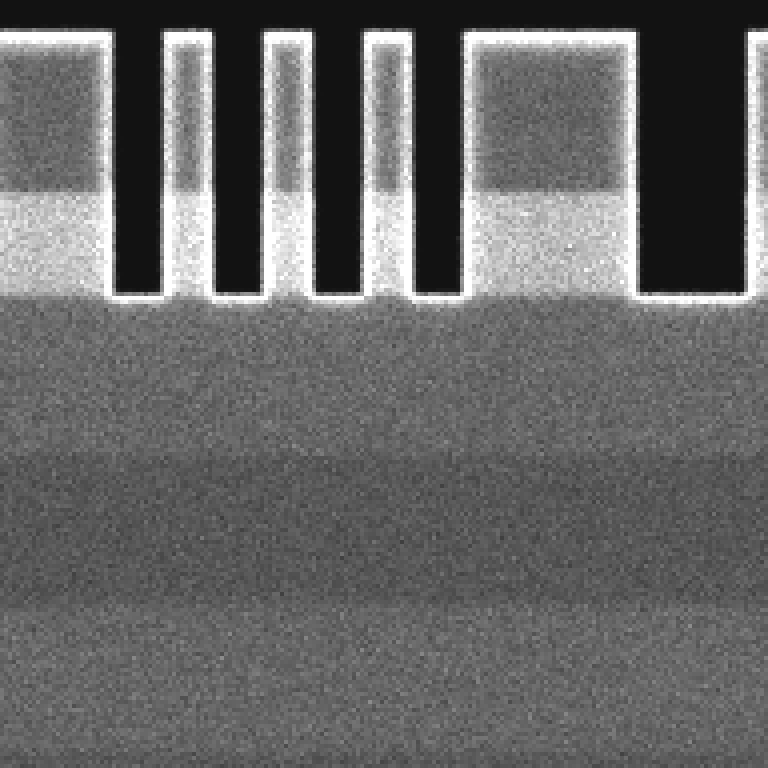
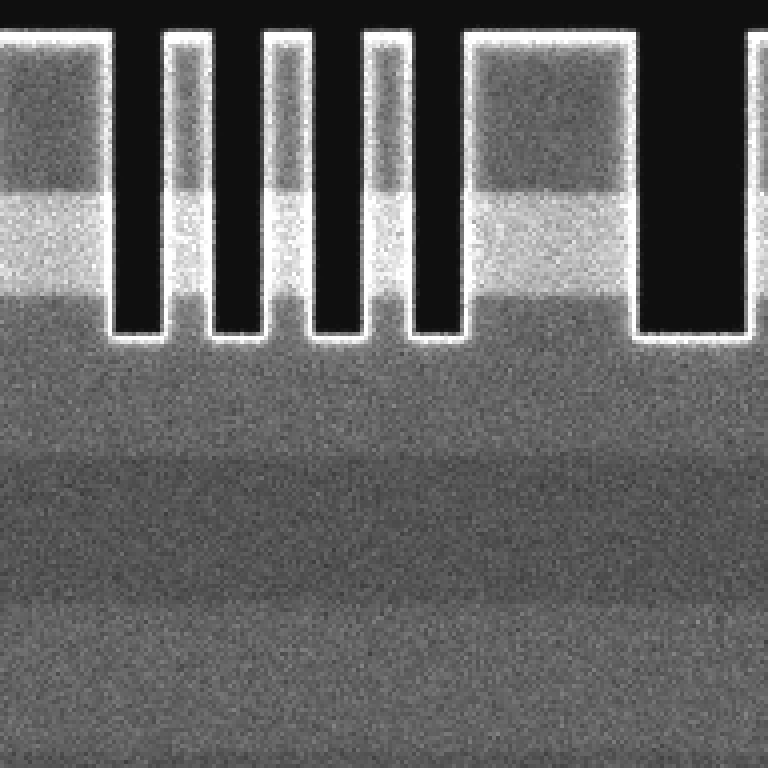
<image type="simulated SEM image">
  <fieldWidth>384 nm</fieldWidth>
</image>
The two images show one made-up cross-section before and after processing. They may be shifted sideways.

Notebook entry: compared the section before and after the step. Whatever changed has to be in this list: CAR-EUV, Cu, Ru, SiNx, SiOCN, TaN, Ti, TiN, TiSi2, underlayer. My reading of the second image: TiN removed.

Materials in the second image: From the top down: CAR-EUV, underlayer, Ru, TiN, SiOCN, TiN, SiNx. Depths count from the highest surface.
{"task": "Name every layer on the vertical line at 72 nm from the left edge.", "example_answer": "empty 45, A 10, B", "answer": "empty 152, TiN 60, SiOCN 74, TiN 74, SiNx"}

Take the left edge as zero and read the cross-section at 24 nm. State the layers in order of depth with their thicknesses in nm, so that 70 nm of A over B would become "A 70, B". CAR-EUV 48, underlayer 32, Ru 52, TiN 80, SiOCN 74, TiN 74, SiNx